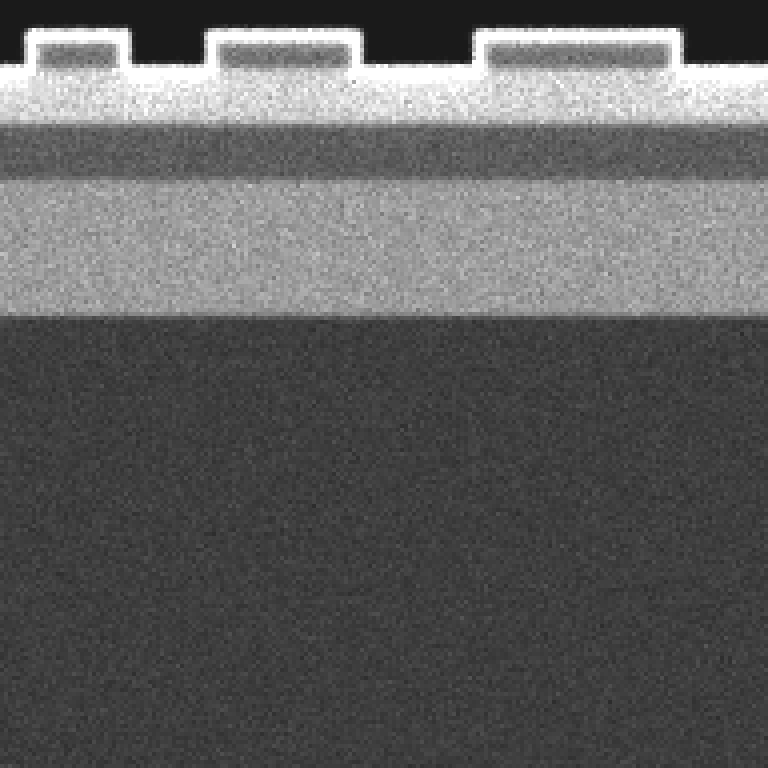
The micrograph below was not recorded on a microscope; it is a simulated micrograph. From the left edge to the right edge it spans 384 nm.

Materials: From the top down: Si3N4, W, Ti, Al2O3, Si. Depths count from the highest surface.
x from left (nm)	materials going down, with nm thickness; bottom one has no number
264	Si3N4 18, W 28, Ti 28, Al2O3 68, Si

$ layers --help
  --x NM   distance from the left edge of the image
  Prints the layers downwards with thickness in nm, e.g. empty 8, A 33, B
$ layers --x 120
Si3N4 18, W 28, Ti 28, Al2O3 68, Si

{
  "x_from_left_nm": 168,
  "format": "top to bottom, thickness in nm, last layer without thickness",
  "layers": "Si3N4 18, W 28, Ti 28, Al2O3 68, Si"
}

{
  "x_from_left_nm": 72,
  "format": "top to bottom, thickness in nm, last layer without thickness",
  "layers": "empty 18, W 28, Ti 28, Al2O3 68, Si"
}